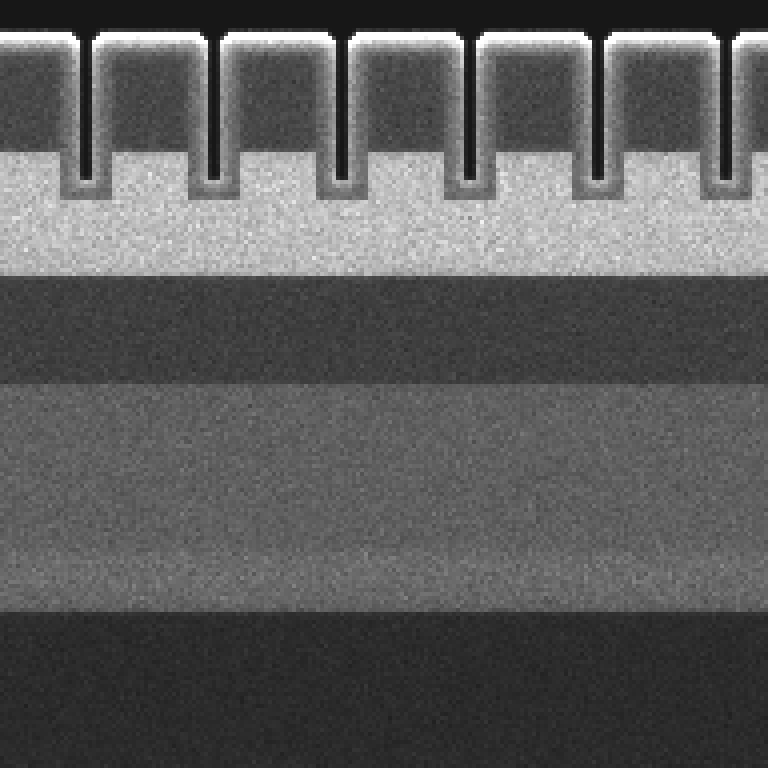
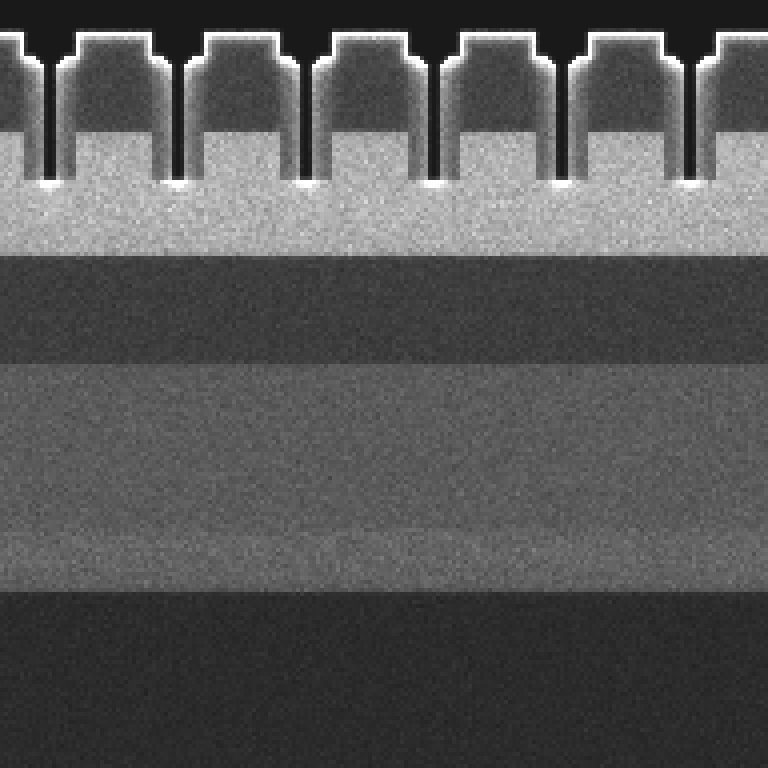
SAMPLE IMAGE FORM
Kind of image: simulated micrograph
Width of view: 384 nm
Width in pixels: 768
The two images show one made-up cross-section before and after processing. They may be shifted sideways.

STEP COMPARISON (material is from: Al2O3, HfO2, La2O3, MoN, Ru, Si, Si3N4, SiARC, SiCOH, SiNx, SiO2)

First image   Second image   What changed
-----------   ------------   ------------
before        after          SiO2, removed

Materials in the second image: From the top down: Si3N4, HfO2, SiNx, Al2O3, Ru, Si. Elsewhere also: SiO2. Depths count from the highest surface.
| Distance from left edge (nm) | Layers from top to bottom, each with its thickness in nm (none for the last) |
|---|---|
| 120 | Si3N4 50, HfO2 62, SiNx 54, Al2O3 84, Ru 30, Si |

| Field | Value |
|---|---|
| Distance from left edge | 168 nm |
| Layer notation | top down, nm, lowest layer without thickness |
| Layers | Si3N4 50, HfO2 62, SiNx 54, Al2O3 84, Ru 30, Si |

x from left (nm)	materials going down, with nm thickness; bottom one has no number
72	Si3N4 50, HfO2 62, SiNx 54, Al2O3 84, Ru 30, Si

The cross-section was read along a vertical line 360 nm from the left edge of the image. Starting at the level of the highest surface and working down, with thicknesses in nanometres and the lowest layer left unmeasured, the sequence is Si3N4 50, HfO2 62, SiNx 54, Al2O3 84, Ru 30, Si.